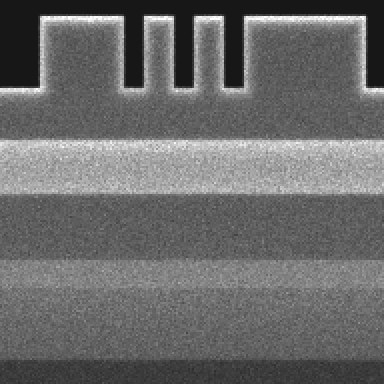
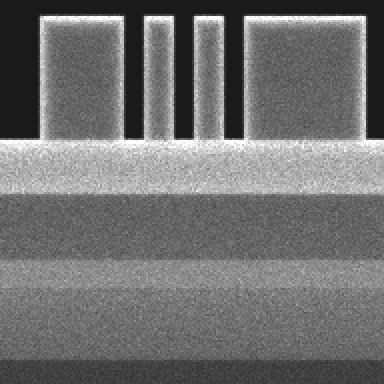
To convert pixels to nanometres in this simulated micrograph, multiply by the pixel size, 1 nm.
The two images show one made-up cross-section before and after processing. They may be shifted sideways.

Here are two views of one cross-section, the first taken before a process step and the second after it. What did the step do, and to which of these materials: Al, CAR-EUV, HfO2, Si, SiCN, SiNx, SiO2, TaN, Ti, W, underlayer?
It removed underlayer.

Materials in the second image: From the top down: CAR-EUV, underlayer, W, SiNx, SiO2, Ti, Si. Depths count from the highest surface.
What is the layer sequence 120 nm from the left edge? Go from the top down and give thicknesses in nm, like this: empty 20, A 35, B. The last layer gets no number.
CAR-EUV 72, underlayer 52, W 54, SiNx 66, SiO2 28, Ti 72, Si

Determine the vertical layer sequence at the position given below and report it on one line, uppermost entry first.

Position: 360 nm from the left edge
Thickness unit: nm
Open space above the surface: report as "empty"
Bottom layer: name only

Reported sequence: CAR-EUV 72, underlayer 52, W 54, SiNx 66, SiO2 28, Ti 72, Si